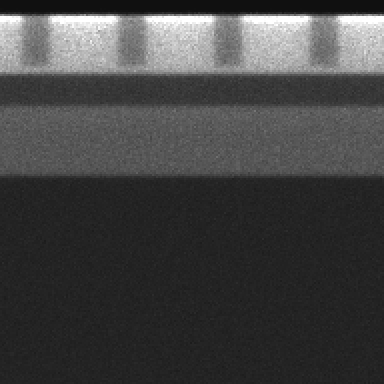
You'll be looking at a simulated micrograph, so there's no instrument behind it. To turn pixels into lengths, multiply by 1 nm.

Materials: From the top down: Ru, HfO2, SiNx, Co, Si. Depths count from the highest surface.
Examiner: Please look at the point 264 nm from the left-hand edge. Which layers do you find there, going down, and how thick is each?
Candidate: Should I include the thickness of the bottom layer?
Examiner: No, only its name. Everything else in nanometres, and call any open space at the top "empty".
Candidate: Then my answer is HfO2 58, SiNx 32, Co 70, Si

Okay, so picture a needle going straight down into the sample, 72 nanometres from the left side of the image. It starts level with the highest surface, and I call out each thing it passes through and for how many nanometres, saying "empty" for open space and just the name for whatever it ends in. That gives HfO2 58, SiNx 32, Co 70, Si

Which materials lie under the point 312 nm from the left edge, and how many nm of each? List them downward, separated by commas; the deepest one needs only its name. Ru 50, HfO2 8, SiNx 32, Co 70, Si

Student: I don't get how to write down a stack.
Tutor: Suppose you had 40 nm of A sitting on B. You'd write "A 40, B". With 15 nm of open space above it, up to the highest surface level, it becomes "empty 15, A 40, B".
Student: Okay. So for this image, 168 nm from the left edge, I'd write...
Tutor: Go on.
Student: HfO2 58, SiNx 32, Co 70, Si